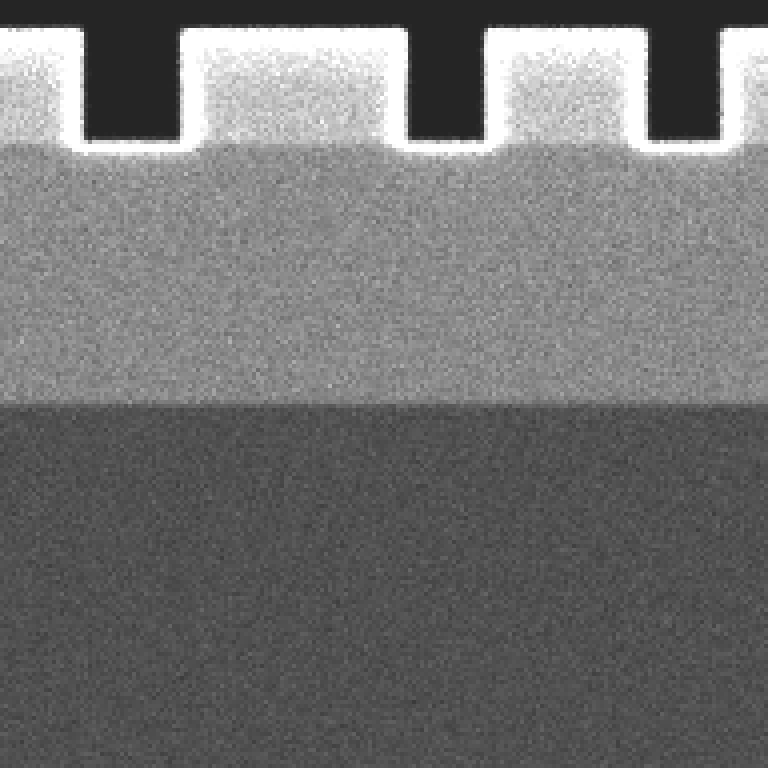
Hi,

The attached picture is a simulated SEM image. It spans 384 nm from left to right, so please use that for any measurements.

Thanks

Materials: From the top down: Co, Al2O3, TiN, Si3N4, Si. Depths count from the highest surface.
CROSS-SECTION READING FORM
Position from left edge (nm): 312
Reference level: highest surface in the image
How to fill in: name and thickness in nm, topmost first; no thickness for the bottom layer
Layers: Co 24, Al2O3 32, TiN 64, Si3N4 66, Si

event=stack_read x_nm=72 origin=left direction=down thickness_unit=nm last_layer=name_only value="empty 56, TiN 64, Si3N4 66, Si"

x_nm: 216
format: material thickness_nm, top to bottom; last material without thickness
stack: empty 56, TiN 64, Si3N4 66, Si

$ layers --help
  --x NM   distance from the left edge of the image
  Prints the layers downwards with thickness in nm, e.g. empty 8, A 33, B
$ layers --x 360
empty 56, TiN 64, Si3N4 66, Si